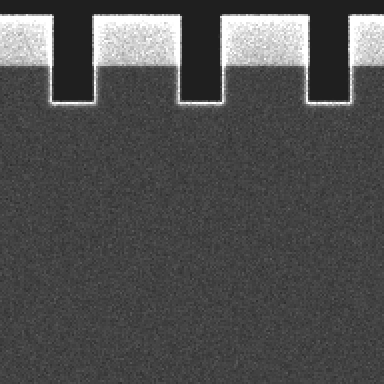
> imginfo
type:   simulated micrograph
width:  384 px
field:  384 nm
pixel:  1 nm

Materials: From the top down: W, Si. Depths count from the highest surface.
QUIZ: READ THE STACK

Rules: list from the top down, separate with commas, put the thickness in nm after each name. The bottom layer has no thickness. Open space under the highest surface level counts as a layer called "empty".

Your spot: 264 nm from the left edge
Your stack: W 50, Si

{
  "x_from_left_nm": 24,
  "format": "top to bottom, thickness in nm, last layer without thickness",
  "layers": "W 50, Si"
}